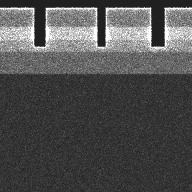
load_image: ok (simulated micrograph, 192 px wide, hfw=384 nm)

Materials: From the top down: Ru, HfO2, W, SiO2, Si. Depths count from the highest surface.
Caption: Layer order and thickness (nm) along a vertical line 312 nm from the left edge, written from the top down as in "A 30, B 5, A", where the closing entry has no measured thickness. empty 78, W 10, SiO2 44, Si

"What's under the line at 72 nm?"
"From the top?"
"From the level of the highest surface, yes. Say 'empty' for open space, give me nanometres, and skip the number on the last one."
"empty 78, W 10, SiO2 44, Si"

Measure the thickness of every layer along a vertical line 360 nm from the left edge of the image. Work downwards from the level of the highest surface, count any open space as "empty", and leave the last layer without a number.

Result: Ru 38, HfO2 26, W 24, SiO2 44, Si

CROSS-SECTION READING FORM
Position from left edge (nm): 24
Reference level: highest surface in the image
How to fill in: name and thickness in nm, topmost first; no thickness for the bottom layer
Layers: Ru 38, HfO2 26, W 24, SiO2 44, Si